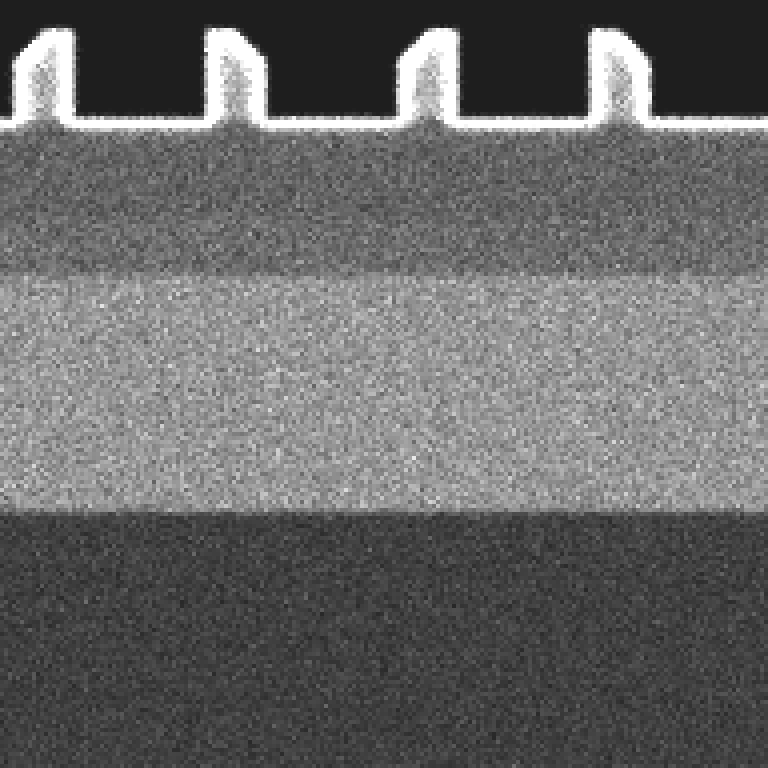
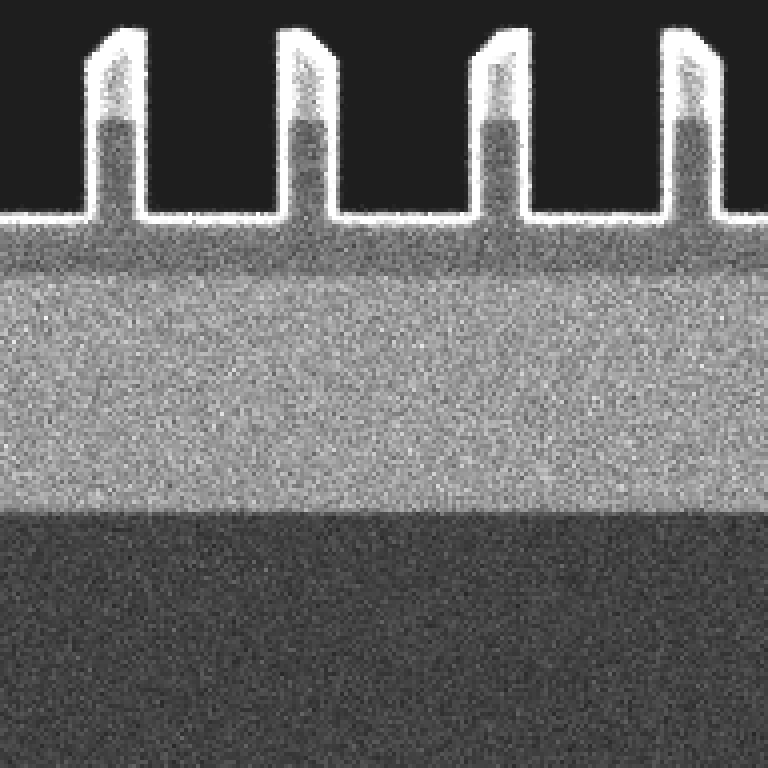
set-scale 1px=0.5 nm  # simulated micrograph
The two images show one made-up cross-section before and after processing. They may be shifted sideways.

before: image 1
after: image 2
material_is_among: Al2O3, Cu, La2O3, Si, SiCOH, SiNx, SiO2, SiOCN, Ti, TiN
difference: SiNx, removed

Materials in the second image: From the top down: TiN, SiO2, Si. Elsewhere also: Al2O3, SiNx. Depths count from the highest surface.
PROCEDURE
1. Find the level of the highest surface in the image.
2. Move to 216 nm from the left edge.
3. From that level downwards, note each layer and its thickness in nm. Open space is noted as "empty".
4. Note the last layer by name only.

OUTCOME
empty 92, TiN 30, SiO2 118, Si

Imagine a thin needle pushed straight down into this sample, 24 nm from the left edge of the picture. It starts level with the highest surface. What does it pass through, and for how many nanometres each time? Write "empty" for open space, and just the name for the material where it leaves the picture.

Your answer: empty 92, TiN 30, SiO2 118, Si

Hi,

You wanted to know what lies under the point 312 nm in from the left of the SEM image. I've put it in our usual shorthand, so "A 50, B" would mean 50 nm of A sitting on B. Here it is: empty 92, TiN 30, SiO2 118, Si